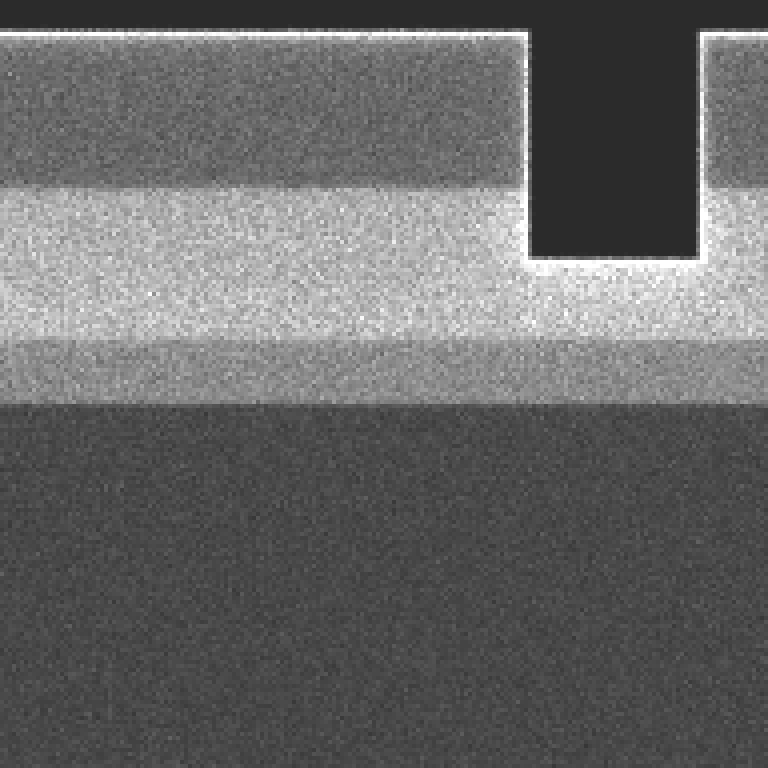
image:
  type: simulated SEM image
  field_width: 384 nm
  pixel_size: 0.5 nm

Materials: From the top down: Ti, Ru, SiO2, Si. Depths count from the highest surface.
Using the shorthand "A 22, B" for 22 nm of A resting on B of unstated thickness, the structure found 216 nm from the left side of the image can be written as Ti 78, Ru 76, SiO2 32, Si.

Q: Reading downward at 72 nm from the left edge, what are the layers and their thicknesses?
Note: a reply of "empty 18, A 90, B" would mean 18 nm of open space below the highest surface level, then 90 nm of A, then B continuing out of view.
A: Ti 78, Ru 76, SiO2 32, Si